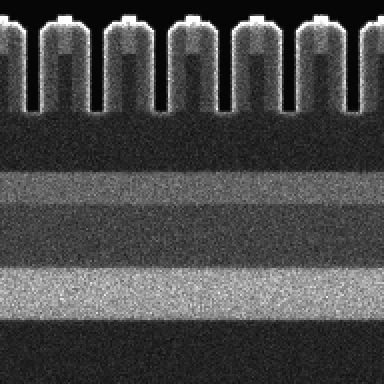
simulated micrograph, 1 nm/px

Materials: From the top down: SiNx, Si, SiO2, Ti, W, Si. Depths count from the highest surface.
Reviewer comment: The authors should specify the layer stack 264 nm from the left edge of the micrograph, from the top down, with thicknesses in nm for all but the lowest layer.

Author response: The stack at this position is empty 6, SiNx 90, Si 60, SiO2 32, Ti 64, W 52, Si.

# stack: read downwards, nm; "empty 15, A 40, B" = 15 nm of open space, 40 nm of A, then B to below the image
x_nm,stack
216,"empty 14, SiNx 82, Si 60, SiO2 32, Ti 64, W 52, Si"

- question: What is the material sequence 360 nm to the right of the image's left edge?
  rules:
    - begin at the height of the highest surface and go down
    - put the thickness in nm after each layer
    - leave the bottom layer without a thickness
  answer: empty 14, SiNx 82, Si 60, SiO2 32, Ti 64, W 52, Si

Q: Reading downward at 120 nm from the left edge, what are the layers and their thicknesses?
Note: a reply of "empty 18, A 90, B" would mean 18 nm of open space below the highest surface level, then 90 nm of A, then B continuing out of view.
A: empty 6, SiNx 90, Si 60, SiO2 32, Ti 64, W 52, Si